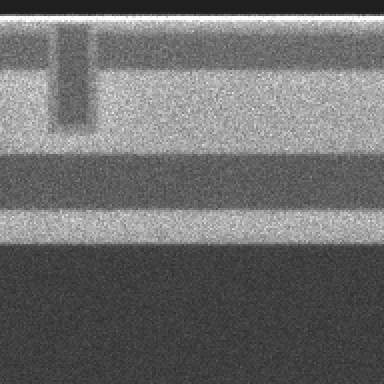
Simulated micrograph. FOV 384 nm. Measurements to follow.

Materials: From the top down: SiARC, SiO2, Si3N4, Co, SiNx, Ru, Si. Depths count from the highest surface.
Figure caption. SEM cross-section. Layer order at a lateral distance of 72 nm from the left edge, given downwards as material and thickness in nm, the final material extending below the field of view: SiARC 108, SiO2 10, Co 20, SiNx 56, Ru 34, Si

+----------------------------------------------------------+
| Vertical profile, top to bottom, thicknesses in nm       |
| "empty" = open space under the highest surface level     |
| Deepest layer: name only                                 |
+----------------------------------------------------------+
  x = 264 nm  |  SiARC 8, SiO2 10, Si3N4 36, Co 84, SiNx 56, Ru 34, Si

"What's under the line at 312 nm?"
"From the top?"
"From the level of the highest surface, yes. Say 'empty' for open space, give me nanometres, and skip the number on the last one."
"SiARC 8, SiO2 10, Si3N4 36, Co 84, SiNx 56, Ru 34, Si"